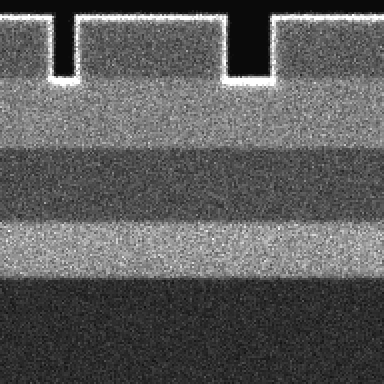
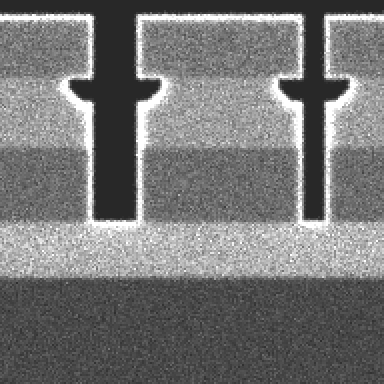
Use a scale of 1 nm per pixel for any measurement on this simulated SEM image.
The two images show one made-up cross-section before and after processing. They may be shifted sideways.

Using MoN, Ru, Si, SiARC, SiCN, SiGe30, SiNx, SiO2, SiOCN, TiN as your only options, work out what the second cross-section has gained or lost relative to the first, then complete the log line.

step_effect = removed SiNx and SiO2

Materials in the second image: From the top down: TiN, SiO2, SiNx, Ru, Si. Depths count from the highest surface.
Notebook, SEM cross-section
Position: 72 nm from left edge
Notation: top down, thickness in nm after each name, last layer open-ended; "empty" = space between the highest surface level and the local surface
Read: TiN 62, empty 16, SiO2 54, SiNx 74, Ru 56, Si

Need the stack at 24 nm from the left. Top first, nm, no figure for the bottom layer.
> TiN 62, SiO2 70, SiNx 74, Ru 56, Si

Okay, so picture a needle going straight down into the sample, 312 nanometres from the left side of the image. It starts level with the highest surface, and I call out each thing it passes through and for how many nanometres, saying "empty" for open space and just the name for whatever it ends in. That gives empty 206, Ru 56, Si